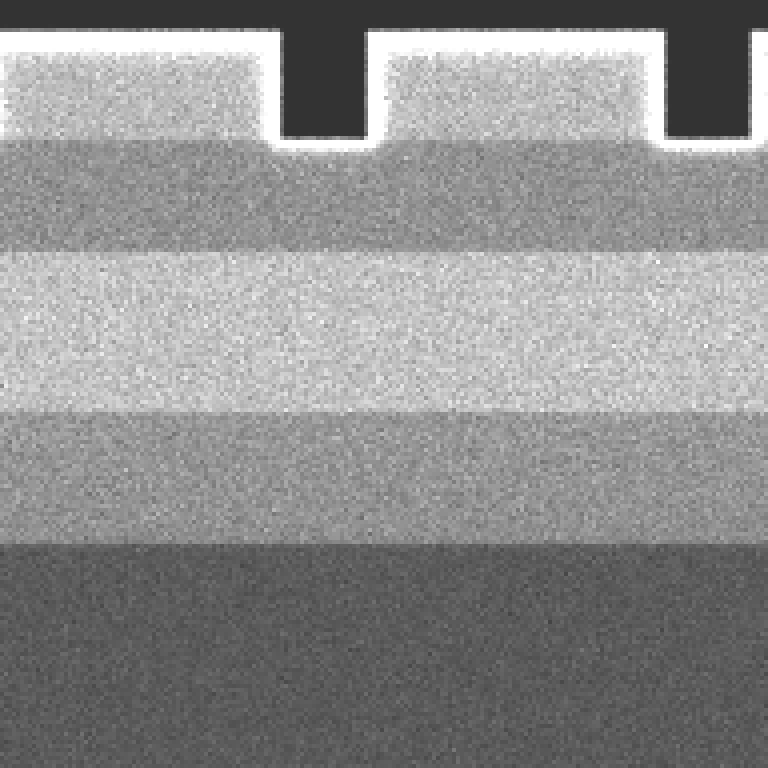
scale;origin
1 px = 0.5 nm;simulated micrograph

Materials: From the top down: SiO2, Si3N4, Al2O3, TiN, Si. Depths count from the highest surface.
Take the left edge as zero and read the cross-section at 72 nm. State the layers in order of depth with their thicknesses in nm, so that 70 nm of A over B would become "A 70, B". SiO2 54, Si3N4 56, Al2O3 80, TiN 66, Si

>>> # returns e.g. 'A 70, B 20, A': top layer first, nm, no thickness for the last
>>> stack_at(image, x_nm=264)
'SiO2 54, Si3N4 56, Al2O3 80, TiN 66, Si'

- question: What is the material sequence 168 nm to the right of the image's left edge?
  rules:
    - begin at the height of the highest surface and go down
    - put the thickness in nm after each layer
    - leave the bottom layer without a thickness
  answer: empty 54, Si3N4 56, Al2O3 80, TiN 66, Si